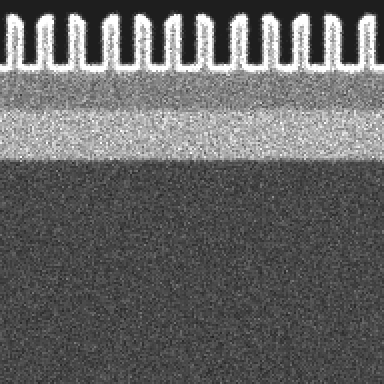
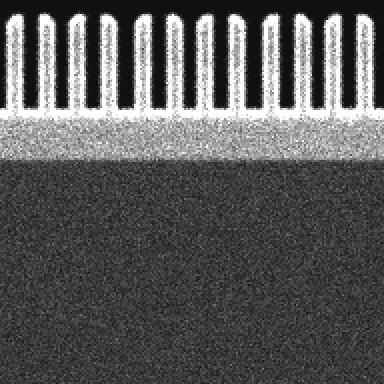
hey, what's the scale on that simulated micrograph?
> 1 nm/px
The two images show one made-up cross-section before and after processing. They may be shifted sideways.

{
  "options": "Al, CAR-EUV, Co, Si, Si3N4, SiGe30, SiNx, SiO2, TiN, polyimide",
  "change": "removed",
  "material": "Si3N4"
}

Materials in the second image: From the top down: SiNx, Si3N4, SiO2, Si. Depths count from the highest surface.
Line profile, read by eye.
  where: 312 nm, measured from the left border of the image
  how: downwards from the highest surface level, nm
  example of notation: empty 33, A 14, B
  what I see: empty 94, SiO2 50, Si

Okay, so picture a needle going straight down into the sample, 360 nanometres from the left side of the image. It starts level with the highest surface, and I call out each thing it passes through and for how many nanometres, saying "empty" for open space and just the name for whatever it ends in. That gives SiNx 50, Si3N4 44, SiO2 50, Si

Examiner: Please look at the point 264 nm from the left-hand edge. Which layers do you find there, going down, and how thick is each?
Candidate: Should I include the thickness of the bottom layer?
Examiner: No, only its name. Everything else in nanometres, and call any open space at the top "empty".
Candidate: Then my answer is empty 6, SiNx 44, Si3N4 44, SiO2 50, Si